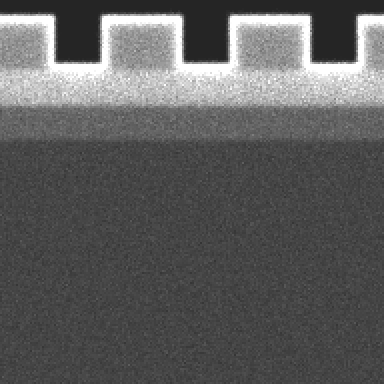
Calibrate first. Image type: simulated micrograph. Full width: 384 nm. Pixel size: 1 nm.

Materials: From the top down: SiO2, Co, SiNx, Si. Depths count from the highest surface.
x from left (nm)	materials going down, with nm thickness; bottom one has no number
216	empty 48, SiO2 6, Co 36, SiNx 34, Si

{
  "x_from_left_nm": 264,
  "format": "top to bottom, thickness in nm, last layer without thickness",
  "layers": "SiO2 54, Co 36, SiNx 34, Si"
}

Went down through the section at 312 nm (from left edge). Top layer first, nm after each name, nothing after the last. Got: empty 48, SiO2 6, Co 36, SiNx 34, Si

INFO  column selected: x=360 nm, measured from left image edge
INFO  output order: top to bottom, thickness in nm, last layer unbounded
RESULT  SiO2 54, Co 36, SiNx 34, Si